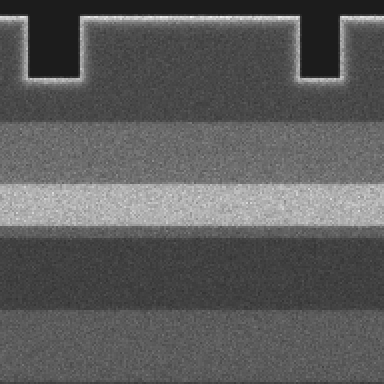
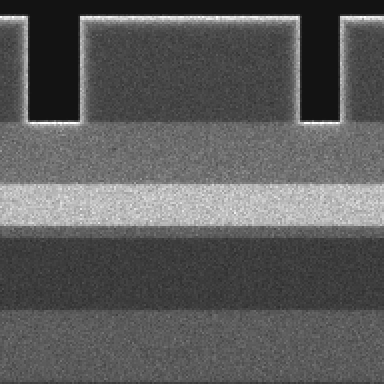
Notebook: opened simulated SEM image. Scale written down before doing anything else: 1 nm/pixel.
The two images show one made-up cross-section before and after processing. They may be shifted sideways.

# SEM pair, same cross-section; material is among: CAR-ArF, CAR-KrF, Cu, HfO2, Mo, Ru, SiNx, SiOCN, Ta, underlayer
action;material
removed;underlayer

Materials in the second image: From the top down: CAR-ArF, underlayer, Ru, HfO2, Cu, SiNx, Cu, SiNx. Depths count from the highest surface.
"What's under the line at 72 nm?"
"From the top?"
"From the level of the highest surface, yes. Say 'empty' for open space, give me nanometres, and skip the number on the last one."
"empty 106, Ru 62, HfO2 42, Cu 12, SiNx 72, Cu 72, SiNx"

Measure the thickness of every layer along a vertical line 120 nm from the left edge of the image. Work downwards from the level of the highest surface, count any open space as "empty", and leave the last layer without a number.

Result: CAR-ArF 62, underlayer 44, Ru 62, HfO2 42, Cu 12, SiNx 72, Cu 72, SiNx